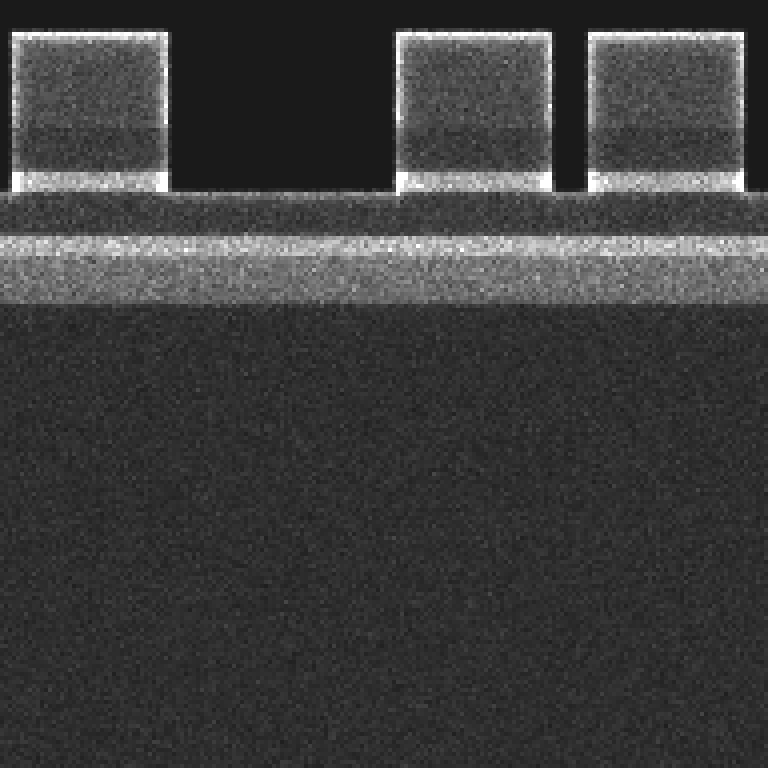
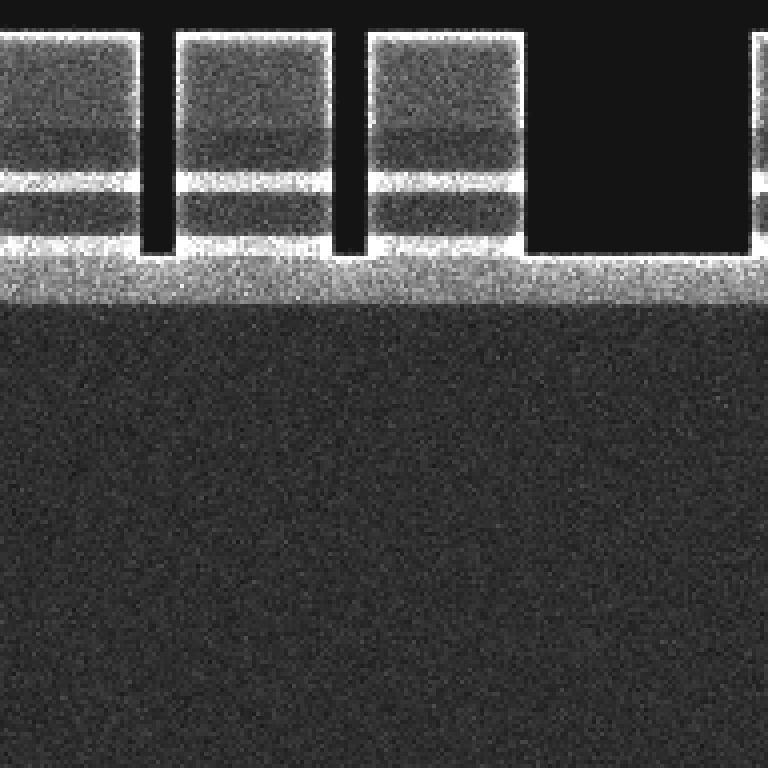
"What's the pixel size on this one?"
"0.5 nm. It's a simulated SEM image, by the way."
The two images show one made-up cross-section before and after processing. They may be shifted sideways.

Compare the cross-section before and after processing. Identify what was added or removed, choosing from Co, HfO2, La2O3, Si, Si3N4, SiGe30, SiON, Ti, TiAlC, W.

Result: HfO2 and SiGe30 removed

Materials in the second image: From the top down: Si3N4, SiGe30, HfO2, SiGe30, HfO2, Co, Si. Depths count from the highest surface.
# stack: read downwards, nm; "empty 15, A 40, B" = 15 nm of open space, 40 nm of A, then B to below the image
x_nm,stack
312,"empty 112, Co 24, Si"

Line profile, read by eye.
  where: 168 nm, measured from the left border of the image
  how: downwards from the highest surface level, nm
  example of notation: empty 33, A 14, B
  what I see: empty 112, Co 24, Si